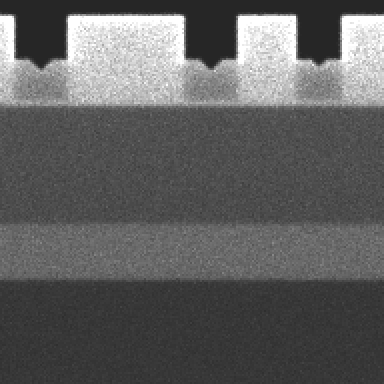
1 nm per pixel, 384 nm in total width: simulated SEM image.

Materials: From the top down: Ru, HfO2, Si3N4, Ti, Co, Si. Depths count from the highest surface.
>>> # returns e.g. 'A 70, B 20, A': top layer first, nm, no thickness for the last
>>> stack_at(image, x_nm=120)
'HfO2 90, Si3N4 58, Ti 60, Co 56, Si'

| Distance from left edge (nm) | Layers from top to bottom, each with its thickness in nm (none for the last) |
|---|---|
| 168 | HfO2 90, Si3N4 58, Ti 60, Co 56, Si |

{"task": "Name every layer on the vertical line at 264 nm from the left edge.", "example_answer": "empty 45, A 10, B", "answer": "HfO2 90, Si3N4 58, Ti 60, Co 56, Si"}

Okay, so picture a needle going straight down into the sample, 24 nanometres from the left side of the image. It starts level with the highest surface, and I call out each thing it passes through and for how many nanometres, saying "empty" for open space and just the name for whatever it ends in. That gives empty 44, Ru 40, HfO2 6, Si3N4 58, Ti 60, Co 56, Si